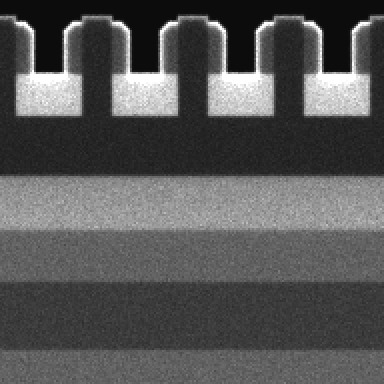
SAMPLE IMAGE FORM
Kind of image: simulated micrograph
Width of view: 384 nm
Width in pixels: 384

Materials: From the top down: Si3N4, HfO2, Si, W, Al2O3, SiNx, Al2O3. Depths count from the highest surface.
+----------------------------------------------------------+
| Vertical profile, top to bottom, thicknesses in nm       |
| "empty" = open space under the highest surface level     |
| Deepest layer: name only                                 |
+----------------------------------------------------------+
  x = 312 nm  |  empty 6, Si3N4 52, HfO2 42, Si 60, W 54, Al2O3 52, SiNx 68, Al2O3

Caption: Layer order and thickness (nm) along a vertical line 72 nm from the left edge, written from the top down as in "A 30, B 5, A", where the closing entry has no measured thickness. empty 6, Si3N4 52, HfO2 42, Si 60, W 54, Al2O3 52, SiNx 68, Al2O3